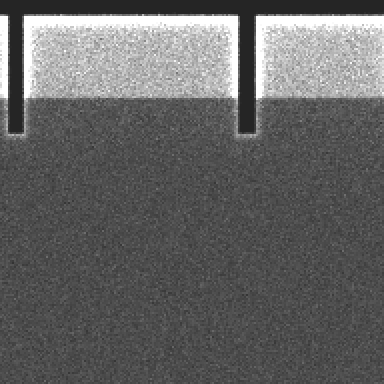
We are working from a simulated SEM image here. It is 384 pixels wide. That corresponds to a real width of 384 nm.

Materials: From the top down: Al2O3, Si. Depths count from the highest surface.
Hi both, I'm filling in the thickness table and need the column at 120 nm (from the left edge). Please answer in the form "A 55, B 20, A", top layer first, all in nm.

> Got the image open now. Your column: Al2O3 82, Si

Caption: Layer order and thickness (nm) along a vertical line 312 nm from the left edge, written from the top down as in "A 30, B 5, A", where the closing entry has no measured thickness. Al2O3 82, Si